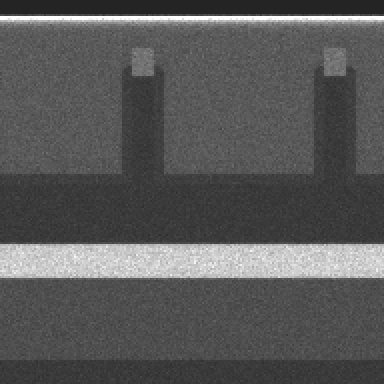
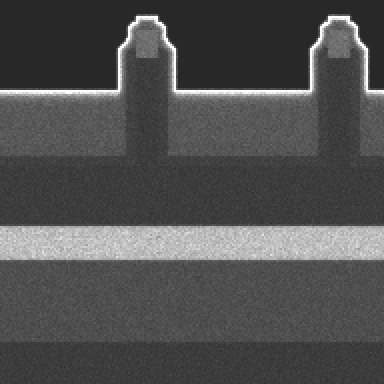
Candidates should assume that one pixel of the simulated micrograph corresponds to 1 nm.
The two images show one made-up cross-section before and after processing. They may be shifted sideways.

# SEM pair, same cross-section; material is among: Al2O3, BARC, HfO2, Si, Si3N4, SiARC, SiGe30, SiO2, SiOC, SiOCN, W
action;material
removed;SiARC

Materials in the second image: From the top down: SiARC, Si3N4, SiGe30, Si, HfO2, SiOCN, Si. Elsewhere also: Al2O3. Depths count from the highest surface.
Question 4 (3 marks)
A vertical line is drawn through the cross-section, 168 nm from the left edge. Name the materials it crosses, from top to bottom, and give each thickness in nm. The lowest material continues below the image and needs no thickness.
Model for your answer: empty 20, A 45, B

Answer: empty 26, Si3N4 114, SiGe30 10, Si 60, HfO2 34, SiOCN 82, Si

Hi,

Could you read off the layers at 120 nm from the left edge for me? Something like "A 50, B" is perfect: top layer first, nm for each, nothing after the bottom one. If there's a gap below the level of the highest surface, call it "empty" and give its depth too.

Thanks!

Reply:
empty 30, Si3N4 110, SiGe30 10, Si 60, HfO2 34, SiOCN 82, Si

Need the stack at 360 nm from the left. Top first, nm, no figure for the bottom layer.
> empty 26, Si3N4 114, SiGe30 10, Si 60, HfO2 34, SiOCN 82, Si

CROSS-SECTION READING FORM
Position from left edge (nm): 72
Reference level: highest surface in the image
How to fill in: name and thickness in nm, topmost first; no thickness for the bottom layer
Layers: empty 74, SiARC 52, Si3N4 14, SiGe30 10, Si 60, HfO2 34, SiOCN 82, Si